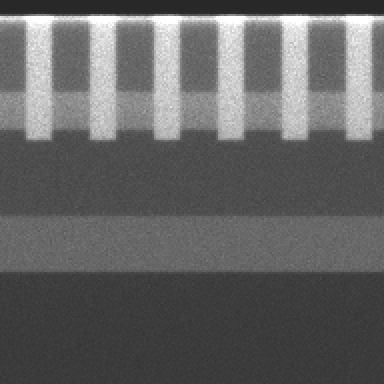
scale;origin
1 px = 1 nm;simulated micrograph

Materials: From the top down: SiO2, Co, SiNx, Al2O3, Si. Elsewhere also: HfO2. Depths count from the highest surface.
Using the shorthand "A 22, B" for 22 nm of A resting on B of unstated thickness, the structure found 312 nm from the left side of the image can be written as SiO2 76, Co 38, SiNx 86, Al2O3 56, Si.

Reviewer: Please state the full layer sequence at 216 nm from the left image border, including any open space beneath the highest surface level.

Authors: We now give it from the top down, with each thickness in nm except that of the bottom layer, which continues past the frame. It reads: SiO2 76, Co 38, SiNx 86, Al2O3 56, Si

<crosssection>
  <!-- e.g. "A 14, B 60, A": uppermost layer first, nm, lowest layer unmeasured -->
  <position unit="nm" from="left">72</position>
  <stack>SiO2 76, Co 38, SiNx 86, Al2O3 56, Si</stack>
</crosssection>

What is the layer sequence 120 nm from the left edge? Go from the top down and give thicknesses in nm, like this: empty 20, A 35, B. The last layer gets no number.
SiO2 76, Co 38, SiNx 86, Al2O3 56, Si